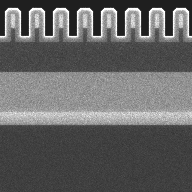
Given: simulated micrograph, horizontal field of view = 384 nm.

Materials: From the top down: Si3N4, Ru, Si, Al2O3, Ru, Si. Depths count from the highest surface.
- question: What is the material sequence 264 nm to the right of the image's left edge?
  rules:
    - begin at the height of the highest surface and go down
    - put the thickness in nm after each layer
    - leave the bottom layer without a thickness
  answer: Si3N4 12, Ru 28, Si 88, Al2O3 80, Ru 26, Si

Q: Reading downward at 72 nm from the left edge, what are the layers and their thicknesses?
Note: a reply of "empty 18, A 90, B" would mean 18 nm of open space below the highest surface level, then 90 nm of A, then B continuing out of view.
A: Si3N4 12, Ru 28, Si 88, Al2O3 80, Ru 26, Si